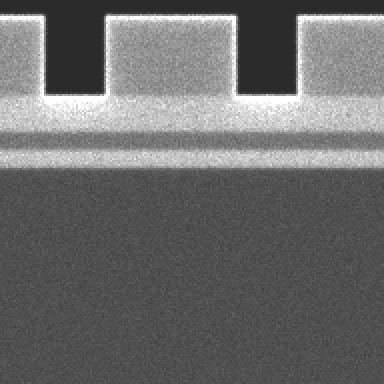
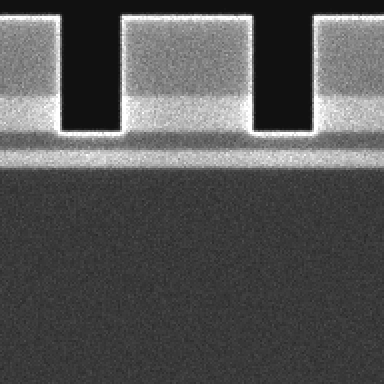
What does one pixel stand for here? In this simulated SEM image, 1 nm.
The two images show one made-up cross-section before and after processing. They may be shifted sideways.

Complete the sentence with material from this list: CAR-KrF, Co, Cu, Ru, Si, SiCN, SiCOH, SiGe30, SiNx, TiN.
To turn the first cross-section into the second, Co must be removed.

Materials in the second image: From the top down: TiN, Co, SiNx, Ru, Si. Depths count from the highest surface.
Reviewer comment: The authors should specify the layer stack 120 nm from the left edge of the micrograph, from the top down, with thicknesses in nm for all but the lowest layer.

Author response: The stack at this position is empty 116, SiNx 18, Ru 18, Si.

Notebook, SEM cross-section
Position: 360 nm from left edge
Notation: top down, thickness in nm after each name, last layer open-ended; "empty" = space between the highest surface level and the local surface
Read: TiN 80, Co 36, SiNx 18, Ru 18, Si